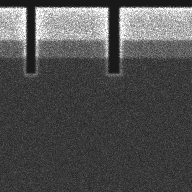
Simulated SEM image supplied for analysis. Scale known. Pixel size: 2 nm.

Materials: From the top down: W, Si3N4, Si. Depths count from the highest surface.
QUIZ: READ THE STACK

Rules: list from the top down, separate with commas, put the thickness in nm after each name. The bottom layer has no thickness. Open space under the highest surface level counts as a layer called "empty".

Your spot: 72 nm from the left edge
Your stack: W 64, Si3N4 36, Si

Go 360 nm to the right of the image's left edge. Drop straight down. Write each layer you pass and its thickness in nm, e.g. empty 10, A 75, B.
W 64, Si3N4 36, Si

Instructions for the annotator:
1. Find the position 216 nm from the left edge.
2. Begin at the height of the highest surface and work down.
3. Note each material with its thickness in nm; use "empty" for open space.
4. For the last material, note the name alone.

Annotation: empty 132, Si